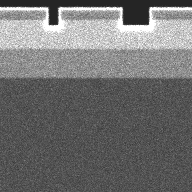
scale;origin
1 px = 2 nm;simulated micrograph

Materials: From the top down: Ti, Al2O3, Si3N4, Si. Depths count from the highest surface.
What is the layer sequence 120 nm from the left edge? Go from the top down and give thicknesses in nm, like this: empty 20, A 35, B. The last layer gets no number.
Ti 24, Al2O3 58, Si3N4 58, Si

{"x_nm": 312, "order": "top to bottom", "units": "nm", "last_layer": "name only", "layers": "Ti 24, Al2O3 58, Si3N4 58, Si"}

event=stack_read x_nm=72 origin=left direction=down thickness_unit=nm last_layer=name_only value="Ti 24, Al2O3 58, Si3N4 58, Si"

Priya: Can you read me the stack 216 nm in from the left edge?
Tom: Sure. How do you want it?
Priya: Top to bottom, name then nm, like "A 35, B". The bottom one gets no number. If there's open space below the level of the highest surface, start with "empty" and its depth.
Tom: Ti 24, Al2O3 58, Si3N4 58, Si